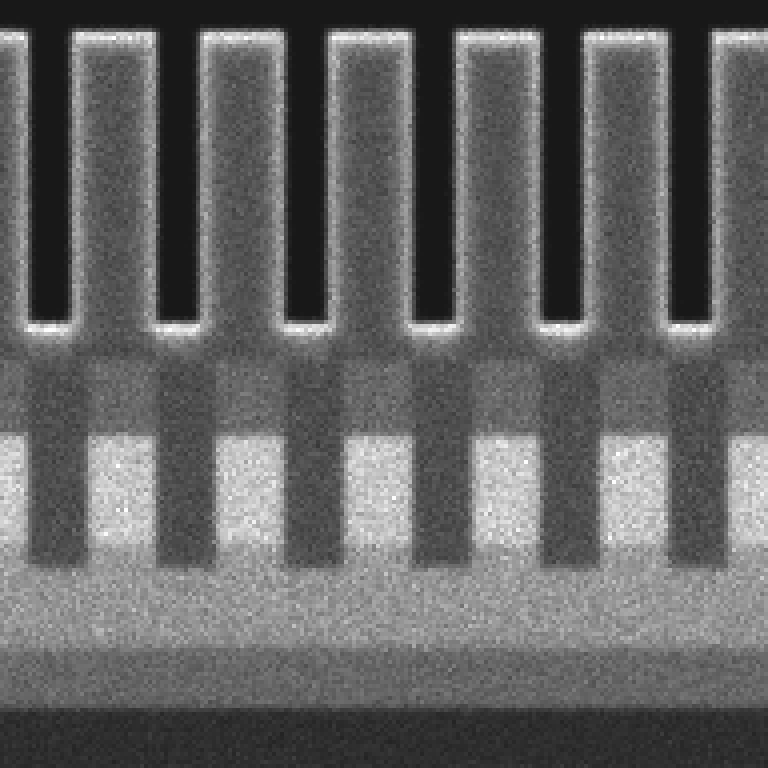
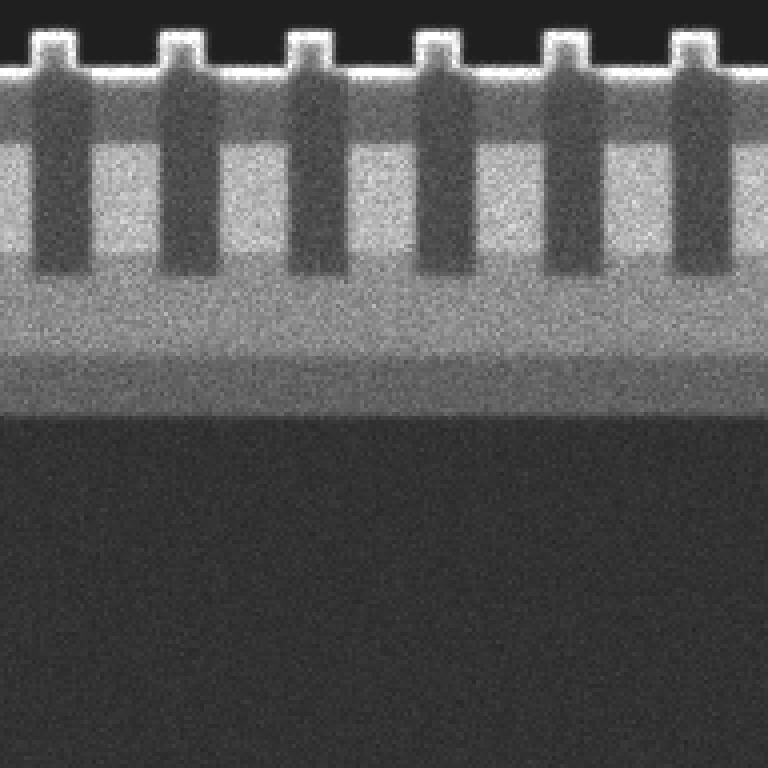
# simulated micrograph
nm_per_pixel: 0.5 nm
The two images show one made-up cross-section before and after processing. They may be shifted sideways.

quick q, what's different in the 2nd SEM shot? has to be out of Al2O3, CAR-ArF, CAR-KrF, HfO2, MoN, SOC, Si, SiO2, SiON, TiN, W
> SOC removed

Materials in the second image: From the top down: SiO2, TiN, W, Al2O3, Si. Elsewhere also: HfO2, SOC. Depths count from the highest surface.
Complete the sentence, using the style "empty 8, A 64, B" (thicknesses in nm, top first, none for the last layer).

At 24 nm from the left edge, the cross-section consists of SiO2 18, TiN 104, W 40, Al2O3 30, Si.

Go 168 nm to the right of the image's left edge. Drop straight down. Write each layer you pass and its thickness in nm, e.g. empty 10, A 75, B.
empty 18, TiN 104, W 40, Al2O3 30, Si